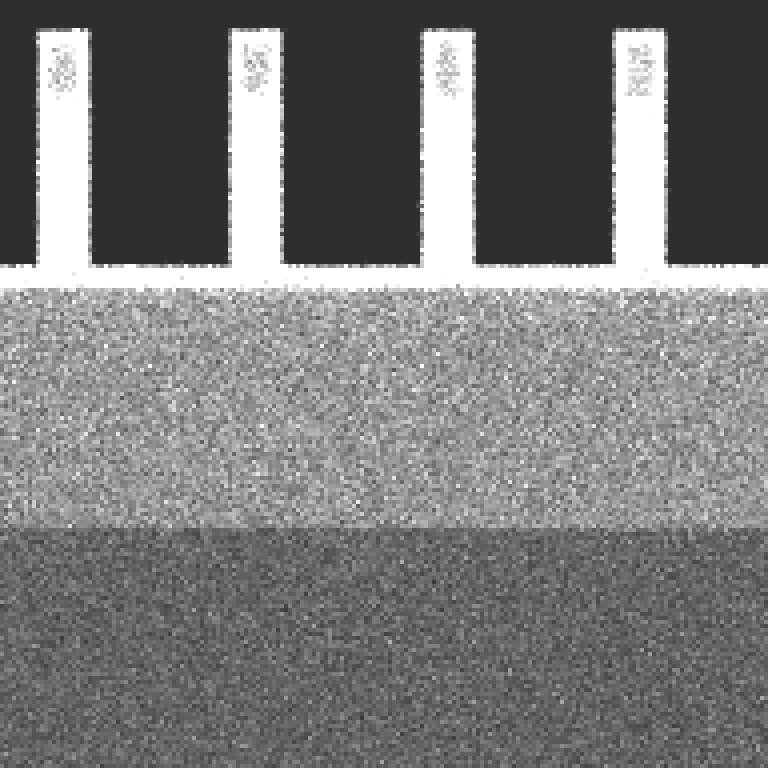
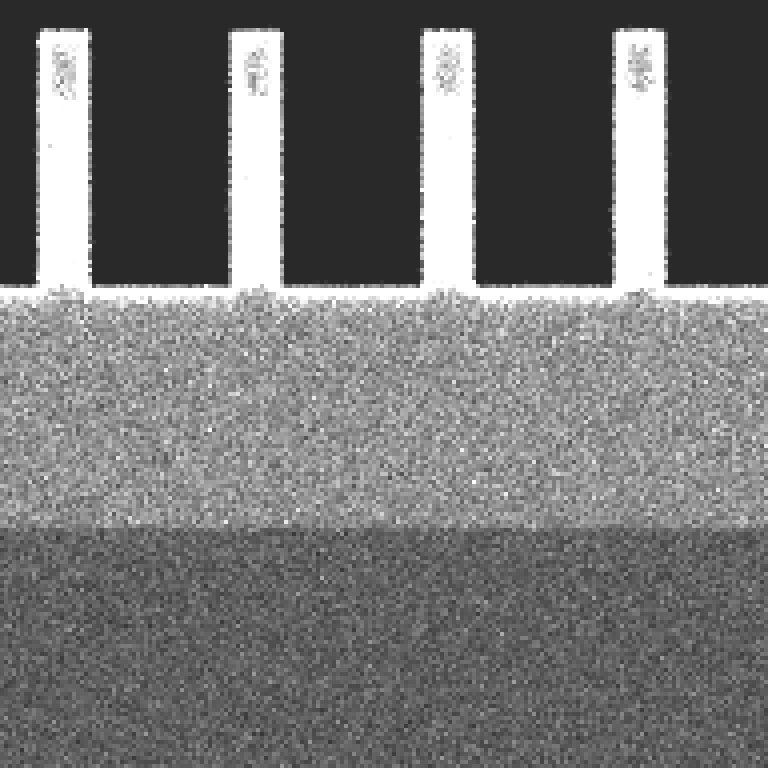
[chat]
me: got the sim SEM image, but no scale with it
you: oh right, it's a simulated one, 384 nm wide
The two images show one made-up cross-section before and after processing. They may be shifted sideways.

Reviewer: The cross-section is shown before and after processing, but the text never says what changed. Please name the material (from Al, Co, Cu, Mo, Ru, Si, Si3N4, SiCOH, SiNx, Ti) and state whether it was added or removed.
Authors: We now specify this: Co, removed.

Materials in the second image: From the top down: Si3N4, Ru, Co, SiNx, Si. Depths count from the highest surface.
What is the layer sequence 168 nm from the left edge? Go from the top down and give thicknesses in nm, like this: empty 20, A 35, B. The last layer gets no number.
empty 128, SiNx 120, Si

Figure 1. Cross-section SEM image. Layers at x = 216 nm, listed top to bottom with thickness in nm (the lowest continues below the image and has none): Si3N4 32, Ru 86, Co 10, SiNx 120, Si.